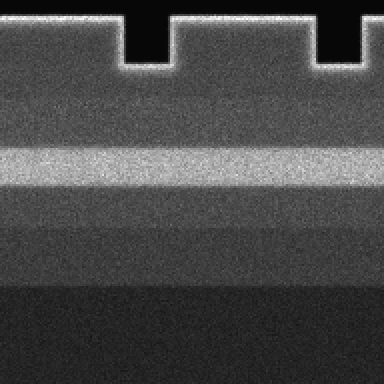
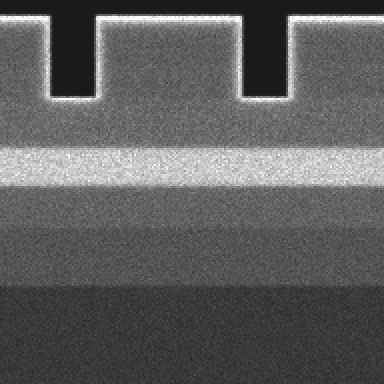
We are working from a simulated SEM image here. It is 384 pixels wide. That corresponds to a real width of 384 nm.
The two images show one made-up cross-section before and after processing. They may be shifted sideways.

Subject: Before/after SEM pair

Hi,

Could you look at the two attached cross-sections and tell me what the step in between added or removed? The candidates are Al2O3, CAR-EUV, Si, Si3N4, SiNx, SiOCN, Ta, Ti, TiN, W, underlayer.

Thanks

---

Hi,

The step removed underlayer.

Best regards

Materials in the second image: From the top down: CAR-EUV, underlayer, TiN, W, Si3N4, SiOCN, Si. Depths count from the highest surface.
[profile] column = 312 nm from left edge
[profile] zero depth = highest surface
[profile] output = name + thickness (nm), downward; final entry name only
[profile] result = CAR-EUV 48, underlayer 34, TiN 50, W 38, Si3N4 42, SiOCN 58, Si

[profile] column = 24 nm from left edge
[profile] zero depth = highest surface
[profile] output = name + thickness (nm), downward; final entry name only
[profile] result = CAR-EUV 48, underlayer 34, TiN 50, W 38, Si3N4 42, SiOCN 58, Si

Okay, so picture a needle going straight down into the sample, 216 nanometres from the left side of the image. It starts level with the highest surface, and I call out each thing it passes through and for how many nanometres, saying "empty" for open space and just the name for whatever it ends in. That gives CAR-EUV 48, underlayer 34, TiN 50, W 38, Si3N4 42, SiOCN 58, Si